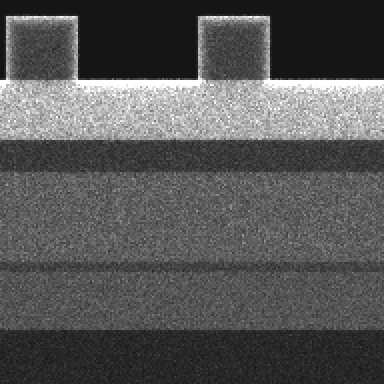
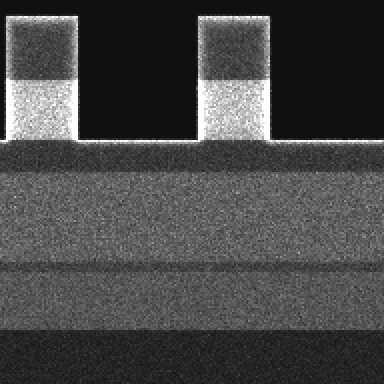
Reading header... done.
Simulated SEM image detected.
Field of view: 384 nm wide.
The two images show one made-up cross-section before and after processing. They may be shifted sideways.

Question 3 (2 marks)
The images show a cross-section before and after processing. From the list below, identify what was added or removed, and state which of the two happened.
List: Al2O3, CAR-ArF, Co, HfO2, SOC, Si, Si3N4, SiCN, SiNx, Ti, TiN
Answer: HfO2 was removed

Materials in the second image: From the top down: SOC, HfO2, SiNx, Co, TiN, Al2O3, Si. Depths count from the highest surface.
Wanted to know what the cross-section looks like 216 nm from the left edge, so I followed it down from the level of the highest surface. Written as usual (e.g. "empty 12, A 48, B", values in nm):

SOC 64, HfO2 60, SiNx 32, Co 90, TiN 10, Al2O3 58, Si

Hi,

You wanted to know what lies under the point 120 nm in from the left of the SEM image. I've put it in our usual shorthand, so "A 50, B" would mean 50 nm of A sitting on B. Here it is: empty 124, SiNx 32, Co 90, TiN 10, Al2O3 58, Si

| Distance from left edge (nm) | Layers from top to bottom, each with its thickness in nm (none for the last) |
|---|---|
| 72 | SOC 64, HfO2 60, SiNx 32, Co 90, TiN 10, Al2O3 58, Si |